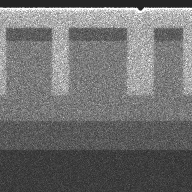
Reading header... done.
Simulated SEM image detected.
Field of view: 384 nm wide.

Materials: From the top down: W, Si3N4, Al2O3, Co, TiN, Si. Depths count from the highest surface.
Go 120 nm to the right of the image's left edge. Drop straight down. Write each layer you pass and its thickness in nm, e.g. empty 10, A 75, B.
W 174, Co 52, TiN 58, Si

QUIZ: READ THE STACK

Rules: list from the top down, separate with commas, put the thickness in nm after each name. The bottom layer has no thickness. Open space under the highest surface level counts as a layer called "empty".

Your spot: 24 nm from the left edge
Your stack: W 40, Si3N4 26, Al2O3 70, Co 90, TiN 58, Si